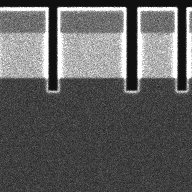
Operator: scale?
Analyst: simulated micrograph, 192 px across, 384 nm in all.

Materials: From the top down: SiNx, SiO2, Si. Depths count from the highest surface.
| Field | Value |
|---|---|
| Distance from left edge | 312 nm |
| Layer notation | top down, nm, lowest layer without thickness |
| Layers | SiNx 50, SiO2 90, Si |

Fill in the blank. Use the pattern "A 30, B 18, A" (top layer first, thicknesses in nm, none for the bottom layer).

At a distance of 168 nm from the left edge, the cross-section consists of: SiNx 50, SiO2 90, Si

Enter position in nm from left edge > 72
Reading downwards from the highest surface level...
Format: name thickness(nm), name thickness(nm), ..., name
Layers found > SiNx 50, SiO2 90, Si